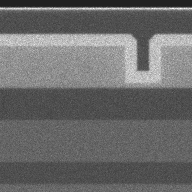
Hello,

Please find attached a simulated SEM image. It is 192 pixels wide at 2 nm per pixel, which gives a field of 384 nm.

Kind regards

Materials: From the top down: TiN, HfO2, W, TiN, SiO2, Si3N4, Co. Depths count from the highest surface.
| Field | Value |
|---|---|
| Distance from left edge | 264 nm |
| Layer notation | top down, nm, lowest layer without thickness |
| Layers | TiN 56, HfO2 94, W 10, TiN 64, SiO2 84, Si3N4 44, Co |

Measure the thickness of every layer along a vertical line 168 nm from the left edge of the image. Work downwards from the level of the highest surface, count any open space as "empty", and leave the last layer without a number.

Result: TiN 52, HfO2 24, W 84, TiN 64, SiO2 84, Si3N4 44, Co